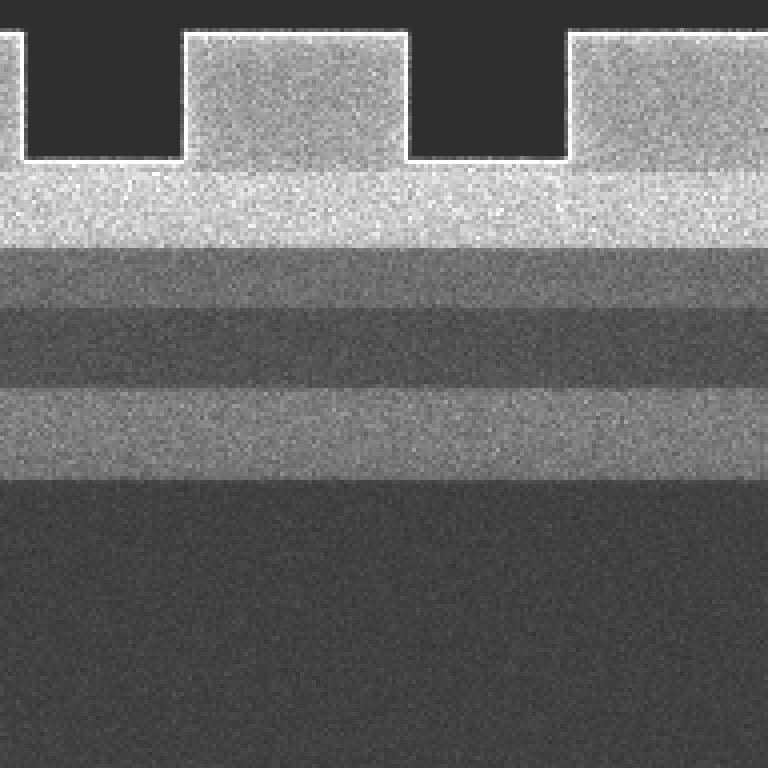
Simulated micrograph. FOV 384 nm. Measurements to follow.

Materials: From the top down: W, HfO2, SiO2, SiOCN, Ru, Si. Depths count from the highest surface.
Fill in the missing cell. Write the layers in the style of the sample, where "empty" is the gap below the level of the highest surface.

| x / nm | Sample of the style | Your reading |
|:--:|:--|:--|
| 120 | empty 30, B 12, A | W 70, HfO2 38, SiO2 30, SiOCN 40, Ru 46, Si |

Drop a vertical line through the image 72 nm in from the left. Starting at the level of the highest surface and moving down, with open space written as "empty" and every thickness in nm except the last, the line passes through empty 64, W 6, HfO2 38, SiO2 30, SiOCN 40, Ru 46, Si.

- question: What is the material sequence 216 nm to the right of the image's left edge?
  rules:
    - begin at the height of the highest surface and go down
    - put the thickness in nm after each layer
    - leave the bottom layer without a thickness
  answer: empty 64, W 6, HfO2 38, SiO2 30, SiOCN 40, Ru 46, Si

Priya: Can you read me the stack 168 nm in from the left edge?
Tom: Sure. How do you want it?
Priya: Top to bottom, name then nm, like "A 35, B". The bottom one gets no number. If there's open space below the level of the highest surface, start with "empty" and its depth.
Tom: W 70, HfO2 38, SiO2 30, SiOCN 40, Ru 46, Si